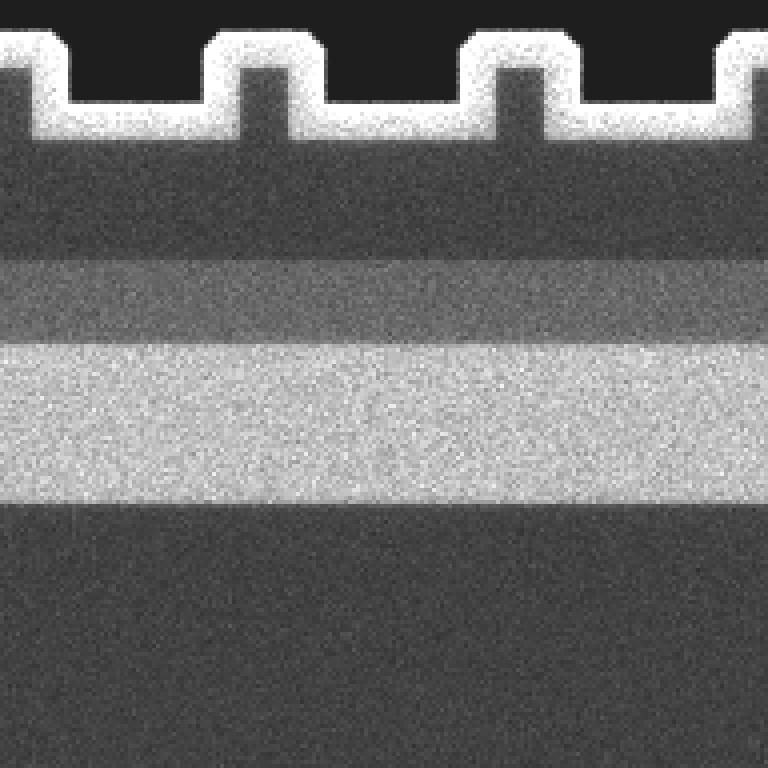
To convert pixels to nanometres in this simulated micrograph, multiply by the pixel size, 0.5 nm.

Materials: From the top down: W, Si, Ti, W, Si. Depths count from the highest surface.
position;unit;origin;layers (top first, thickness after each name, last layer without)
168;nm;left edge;empty 36, W 18, Si 60, Ti 42, W 80, Si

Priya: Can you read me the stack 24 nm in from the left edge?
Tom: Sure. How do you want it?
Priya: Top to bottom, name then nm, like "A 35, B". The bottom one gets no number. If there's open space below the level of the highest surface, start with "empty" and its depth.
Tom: W 54, Si 60, Ti 42, W 80, Si